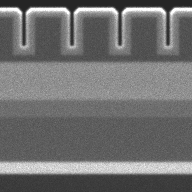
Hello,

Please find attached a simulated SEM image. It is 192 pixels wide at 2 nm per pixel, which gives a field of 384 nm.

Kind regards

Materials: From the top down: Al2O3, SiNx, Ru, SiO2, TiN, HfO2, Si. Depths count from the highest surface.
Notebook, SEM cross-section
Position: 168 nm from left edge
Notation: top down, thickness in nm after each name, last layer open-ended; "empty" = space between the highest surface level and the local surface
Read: Al2O3 18, SiNx 90, Ru 76, SiO2 34, TiN 90, HfO2 24, Si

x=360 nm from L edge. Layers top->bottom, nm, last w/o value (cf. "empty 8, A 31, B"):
Al2O3 18, SiNx 90, Ru 76, SiO2 34, TiN 90, HfO2 24, Si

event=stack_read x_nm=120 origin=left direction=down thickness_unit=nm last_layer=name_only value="Al2O3 18, SiNx 90, Ru 76, SiO2 34, TiN 90, HfO2 24, Si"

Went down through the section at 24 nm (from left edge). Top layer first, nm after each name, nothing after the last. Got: Al2O3 18, SiNx 90, Ru 76, SiO2 34, TiN 90, HfO2 24, Si